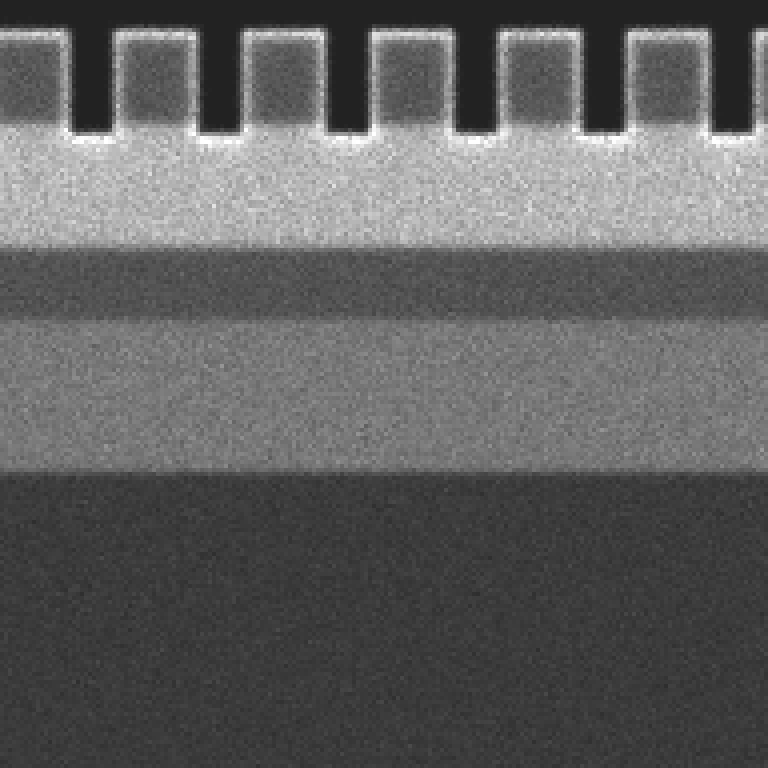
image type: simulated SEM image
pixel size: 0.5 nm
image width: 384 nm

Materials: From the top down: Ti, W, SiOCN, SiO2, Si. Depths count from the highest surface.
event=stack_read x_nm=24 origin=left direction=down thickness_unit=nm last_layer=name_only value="Ti 46, W 62, SiOCN 36, SiO2 76, Si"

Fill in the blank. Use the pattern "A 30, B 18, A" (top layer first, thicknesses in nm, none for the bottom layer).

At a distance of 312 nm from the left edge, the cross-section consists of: empty 52, W 56, SiOCN 36, SiO2 76, Si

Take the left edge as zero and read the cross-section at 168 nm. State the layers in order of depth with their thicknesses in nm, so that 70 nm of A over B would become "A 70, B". empty 52, W 56, SiOCN 36, SiO2 76, Si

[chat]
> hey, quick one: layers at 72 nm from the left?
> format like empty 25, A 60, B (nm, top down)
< Ti 46, W 62, SiOCN 36, SiO2 76, Si